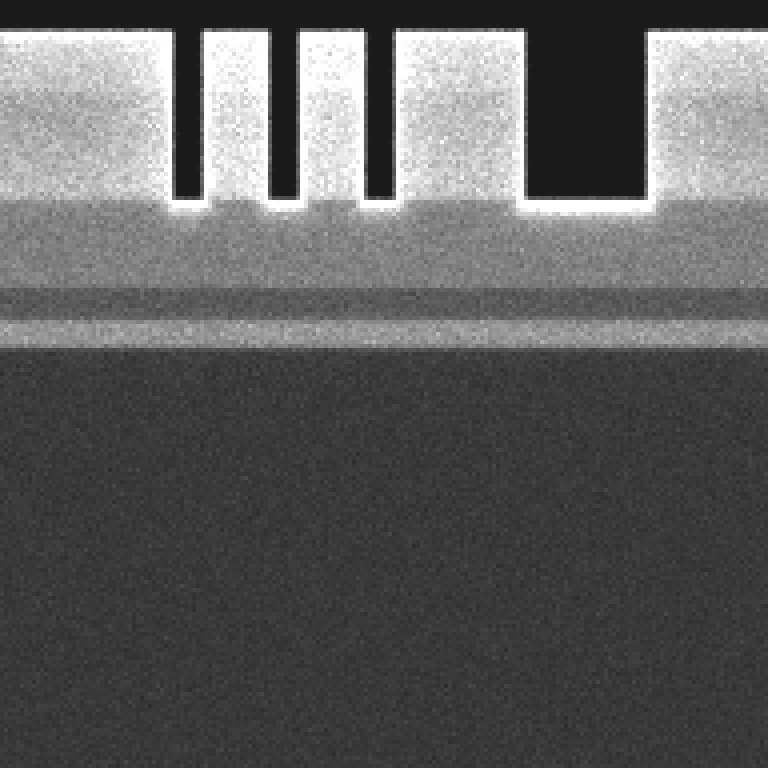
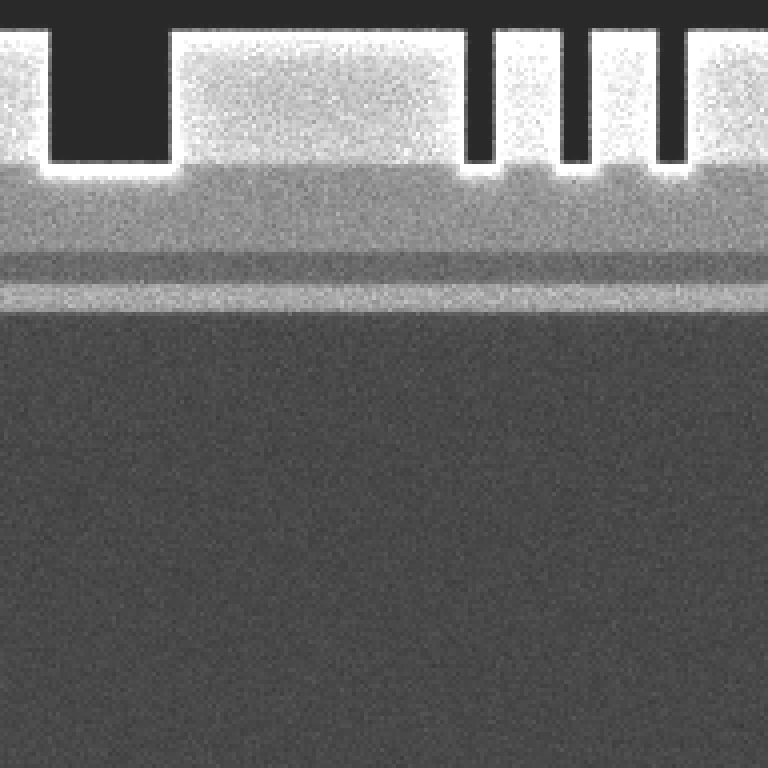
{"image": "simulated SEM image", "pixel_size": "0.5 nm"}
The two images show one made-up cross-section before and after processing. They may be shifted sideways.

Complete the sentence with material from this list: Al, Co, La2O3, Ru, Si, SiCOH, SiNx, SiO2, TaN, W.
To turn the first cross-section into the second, W must be removed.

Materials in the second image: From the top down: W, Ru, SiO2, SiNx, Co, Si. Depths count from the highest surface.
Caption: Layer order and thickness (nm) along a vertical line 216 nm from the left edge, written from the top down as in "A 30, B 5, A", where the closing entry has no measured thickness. W 12, Ru 54, SiO2 44, SiNx 16, Co 14, Si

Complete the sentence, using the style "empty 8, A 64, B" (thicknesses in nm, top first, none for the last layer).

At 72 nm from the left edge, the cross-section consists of empty 66, SiO2 44, SiNx 16, Co 14, Si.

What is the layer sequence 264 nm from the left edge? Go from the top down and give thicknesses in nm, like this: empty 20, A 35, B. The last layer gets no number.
W 12, Ru 54, SiO2 44, SiNx 16, Co 14, Si